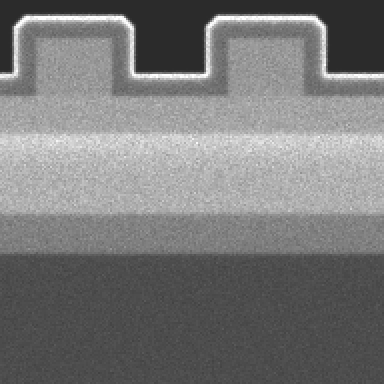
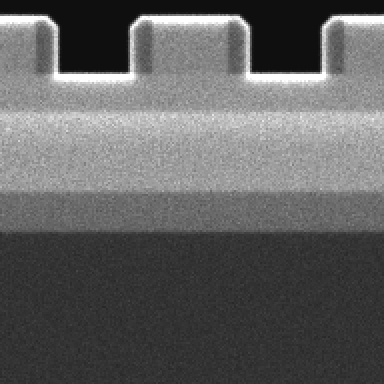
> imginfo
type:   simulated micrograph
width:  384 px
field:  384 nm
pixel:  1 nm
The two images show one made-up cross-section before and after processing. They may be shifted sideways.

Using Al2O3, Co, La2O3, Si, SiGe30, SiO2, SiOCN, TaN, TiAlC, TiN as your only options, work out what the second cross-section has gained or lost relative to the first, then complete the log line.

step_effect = removed SiOCN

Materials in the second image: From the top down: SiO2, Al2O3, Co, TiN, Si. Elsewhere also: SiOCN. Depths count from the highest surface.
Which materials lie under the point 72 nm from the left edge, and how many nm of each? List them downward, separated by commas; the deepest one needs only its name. empty 58, Al2O3 38, Co 80, TiN 40, Si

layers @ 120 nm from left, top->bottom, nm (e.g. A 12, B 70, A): empty 58, Al2O3 38, Co 80, TiN 40, Si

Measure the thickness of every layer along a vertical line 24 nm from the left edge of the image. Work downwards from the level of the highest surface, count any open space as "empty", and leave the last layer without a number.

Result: SiO2 58, Al2O3 38, Co 80, TiN 40, Si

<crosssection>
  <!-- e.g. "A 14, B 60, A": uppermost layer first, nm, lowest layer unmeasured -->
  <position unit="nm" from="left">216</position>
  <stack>SiO2 58, Al2O3 38, Co 80, TiN 40, Si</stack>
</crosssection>